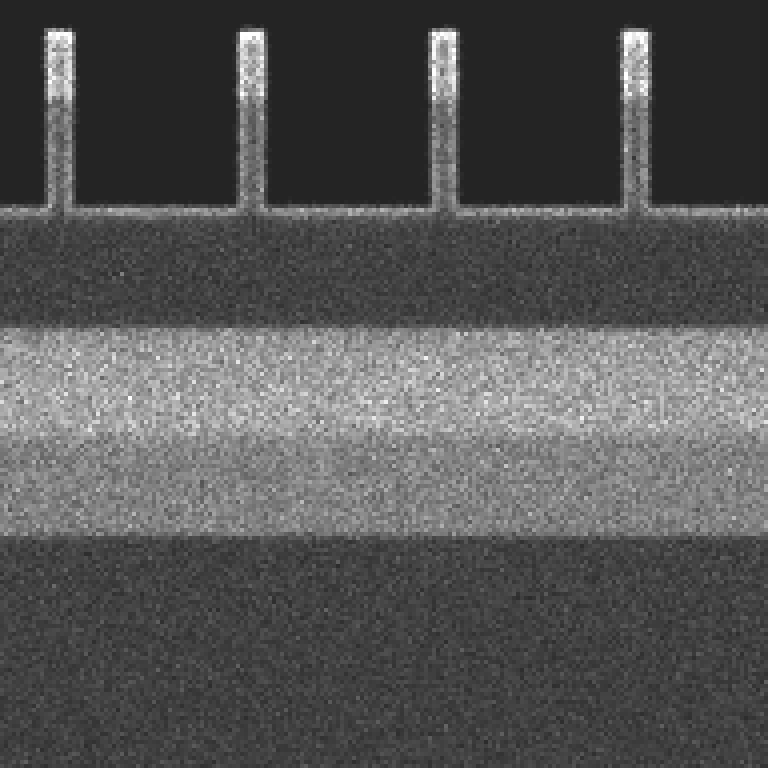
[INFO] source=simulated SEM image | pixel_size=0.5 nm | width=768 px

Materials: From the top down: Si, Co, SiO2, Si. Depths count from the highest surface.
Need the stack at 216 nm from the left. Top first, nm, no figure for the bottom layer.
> Si 148, Co 54, SiO2 50, Si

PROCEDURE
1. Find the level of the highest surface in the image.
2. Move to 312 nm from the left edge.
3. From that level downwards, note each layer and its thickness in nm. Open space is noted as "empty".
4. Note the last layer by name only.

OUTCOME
Si 148, Co 54, SiO2 50, Si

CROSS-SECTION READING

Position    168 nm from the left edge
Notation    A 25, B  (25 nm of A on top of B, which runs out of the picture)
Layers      empty 88, Si 60, Co 54, SiO2 50, Si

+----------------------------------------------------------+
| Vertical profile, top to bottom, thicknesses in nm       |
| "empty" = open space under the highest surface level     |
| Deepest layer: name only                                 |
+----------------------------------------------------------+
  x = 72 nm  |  empty 88, Si 60, Co 54, SiO2 50, Si